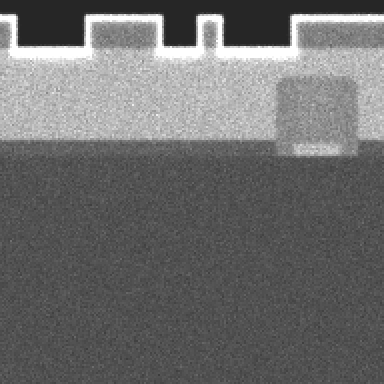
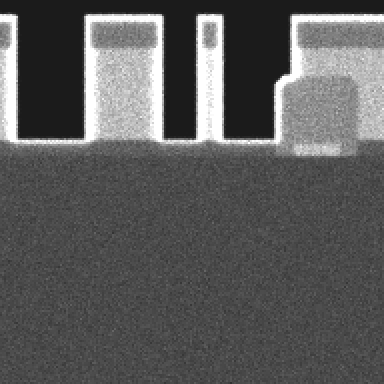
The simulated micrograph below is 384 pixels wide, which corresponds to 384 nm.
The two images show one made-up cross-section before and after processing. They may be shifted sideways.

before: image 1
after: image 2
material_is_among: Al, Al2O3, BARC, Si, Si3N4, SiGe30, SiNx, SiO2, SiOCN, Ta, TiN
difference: SiO2, removed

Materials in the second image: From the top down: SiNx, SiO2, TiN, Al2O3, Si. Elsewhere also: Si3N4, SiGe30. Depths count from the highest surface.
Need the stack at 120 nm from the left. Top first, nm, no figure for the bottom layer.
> SiNx 32, SiO2 92, SiGe30 16, Si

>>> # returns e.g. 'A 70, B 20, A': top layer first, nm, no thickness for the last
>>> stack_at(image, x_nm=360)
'SiNx 32, SiO2 92, SiGe30 16, Si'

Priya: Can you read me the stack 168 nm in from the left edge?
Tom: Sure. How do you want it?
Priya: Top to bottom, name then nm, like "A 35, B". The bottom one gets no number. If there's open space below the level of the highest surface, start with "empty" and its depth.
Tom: empty 124, SiGe30 16, Si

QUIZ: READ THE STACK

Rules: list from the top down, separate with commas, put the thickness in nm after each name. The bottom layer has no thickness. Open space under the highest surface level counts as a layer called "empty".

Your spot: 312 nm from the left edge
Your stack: SiNx 32, SiO2 28, TiN 68, Al2O3 12, Si